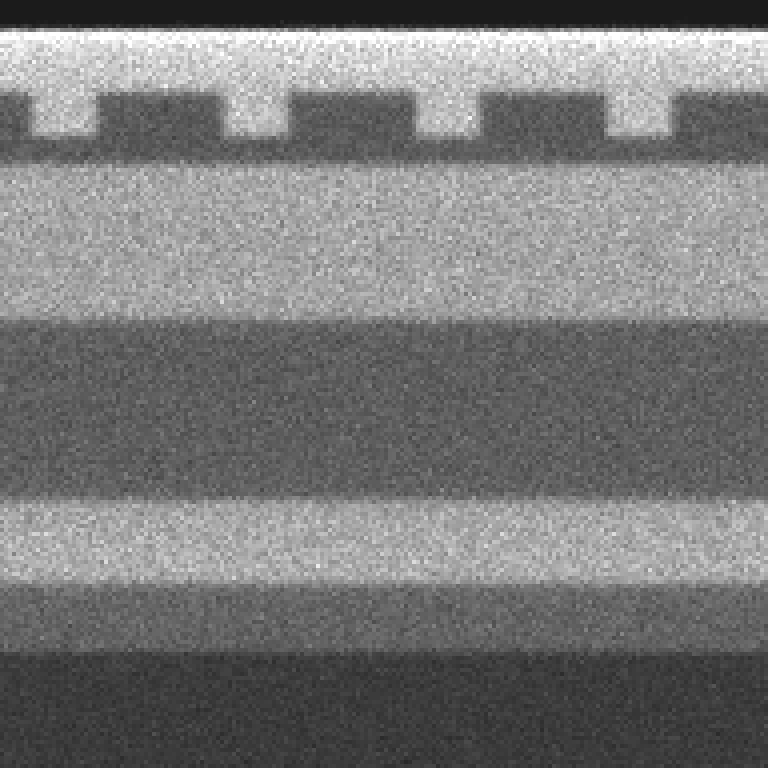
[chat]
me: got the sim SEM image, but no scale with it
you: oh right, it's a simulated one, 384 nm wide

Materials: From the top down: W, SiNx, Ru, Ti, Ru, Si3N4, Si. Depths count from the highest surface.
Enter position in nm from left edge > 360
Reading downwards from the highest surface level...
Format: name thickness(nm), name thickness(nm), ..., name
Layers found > W 30, SiNx 36, Ru 78, Ti 90, Ru 42, Si3N4 34, Si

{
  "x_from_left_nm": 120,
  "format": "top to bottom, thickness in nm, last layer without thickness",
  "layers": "W 52, SiNx 14, Ru 78, Ti 90, Ru 42, Si3N4 34, Si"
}